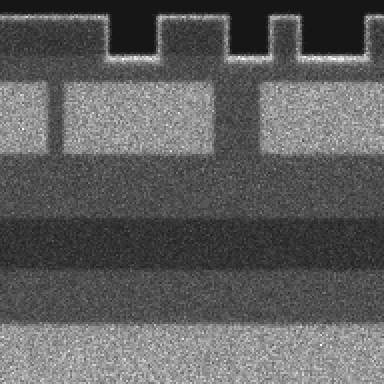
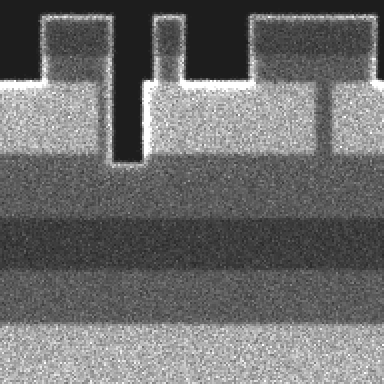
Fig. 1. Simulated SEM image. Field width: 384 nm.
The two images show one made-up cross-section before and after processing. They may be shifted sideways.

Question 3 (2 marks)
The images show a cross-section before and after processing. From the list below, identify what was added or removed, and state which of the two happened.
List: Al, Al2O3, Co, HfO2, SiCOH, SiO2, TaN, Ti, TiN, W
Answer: SiO2 was removed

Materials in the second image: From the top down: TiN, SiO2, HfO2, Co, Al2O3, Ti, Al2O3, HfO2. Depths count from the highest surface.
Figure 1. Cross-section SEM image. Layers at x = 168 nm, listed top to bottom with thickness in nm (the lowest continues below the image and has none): TiN 40, SiO2 26, HfO2 72, Co 34, Al2O3 30, Ti 52, Al2O3 54, HfO2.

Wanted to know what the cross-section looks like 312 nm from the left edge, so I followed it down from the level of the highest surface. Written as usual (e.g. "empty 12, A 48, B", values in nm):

TiN 40, SiO2 26, HfO2 72, Co 34, Al2O3 30, Ti 52, Al2O3 54, HfO2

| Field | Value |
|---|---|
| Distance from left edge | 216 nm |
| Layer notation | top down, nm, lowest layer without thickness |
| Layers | empty 66, HfO2 72, Co 34, Al2O3 30, Ti 52, Al2O3 54, HfO2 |